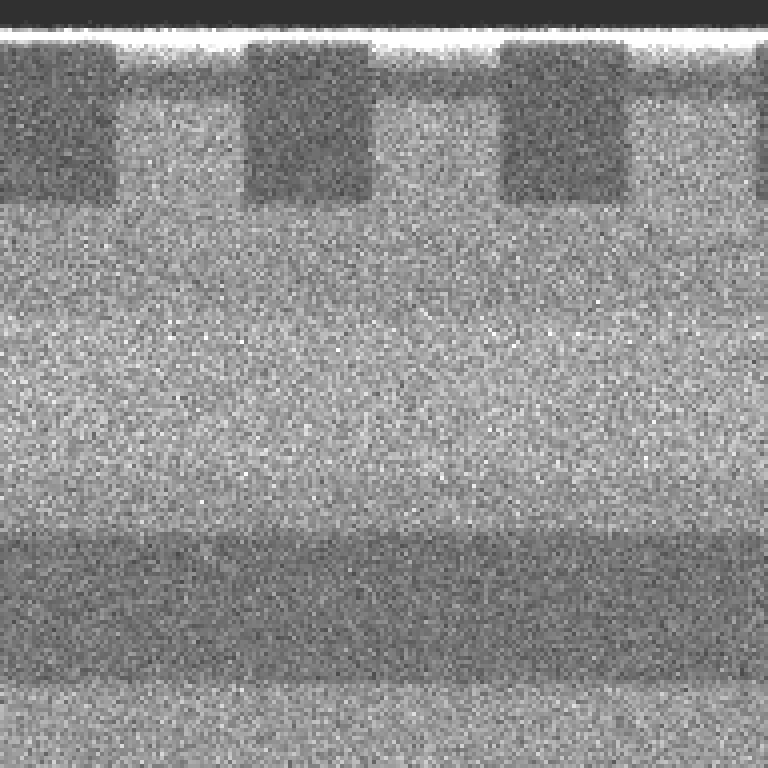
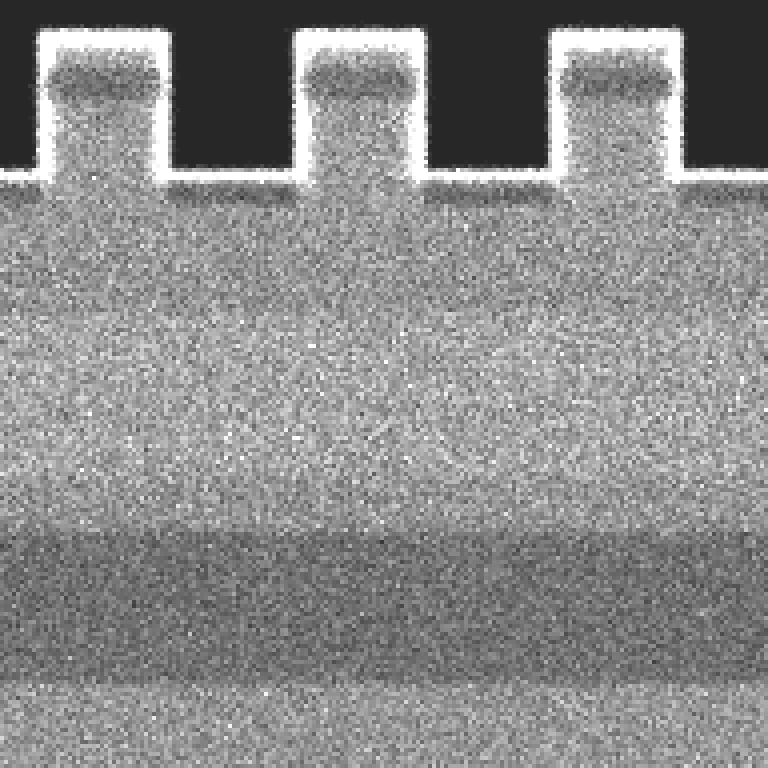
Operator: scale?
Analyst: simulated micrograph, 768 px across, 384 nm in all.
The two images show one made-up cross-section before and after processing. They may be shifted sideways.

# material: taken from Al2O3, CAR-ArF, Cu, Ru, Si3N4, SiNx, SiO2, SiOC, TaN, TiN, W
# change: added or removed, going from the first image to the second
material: SiNx
change: removed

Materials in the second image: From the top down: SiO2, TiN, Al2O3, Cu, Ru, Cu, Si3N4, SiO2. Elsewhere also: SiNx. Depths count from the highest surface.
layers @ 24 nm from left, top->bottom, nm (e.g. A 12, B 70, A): SiO2 18, TiN 16, Al2O3 70, Cu 38, Ru 80, Cu 28, Si3N4 76, SiO2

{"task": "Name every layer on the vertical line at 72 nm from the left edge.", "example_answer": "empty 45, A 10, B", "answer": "SiO2 18, TiN 16, Al2O3 70, Cu 38, Ru 80, Cu 28, Si3N4 76, SiO2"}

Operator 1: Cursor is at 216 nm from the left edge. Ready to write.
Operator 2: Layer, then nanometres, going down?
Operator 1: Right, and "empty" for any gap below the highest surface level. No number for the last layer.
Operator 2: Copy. empty 70, SiNx 16, SiO2 18, Cu 38, Ru 80, Cu 28, Si3N4 76, SiO2